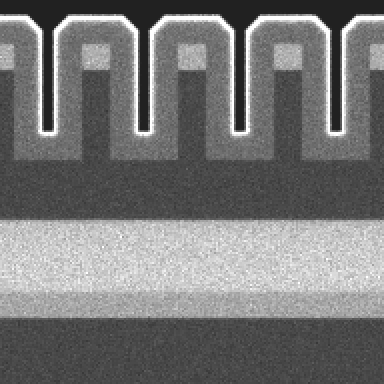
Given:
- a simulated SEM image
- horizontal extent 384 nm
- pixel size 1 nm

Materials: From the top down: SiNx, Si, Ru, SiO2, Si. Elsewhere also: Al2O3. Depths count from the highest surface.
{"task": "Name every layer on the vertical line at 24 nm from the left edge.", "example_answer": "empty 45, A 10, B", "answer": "SiNx 144, Si 60, Ru 72, SiO2 26, Si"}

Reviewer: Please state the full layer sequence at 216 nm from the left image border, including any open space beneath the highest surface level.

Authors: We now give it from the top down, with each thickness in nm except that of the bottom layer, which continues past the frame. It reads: SiNx 144, Si 60, Ru 72, SiO2 26, Si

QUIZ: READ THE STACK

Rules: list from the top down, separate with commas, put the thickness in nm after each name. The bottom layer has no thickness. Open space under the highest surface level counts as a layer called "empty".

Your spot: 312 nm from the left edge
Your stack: SiNx 144, Si 60, Ru 72, SiO2 26, Si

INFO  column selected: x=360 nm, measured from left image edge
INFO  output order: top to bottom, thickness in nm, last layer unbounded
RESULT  SiNx 144, Si 60, Ru 72, SiO2 26, Si